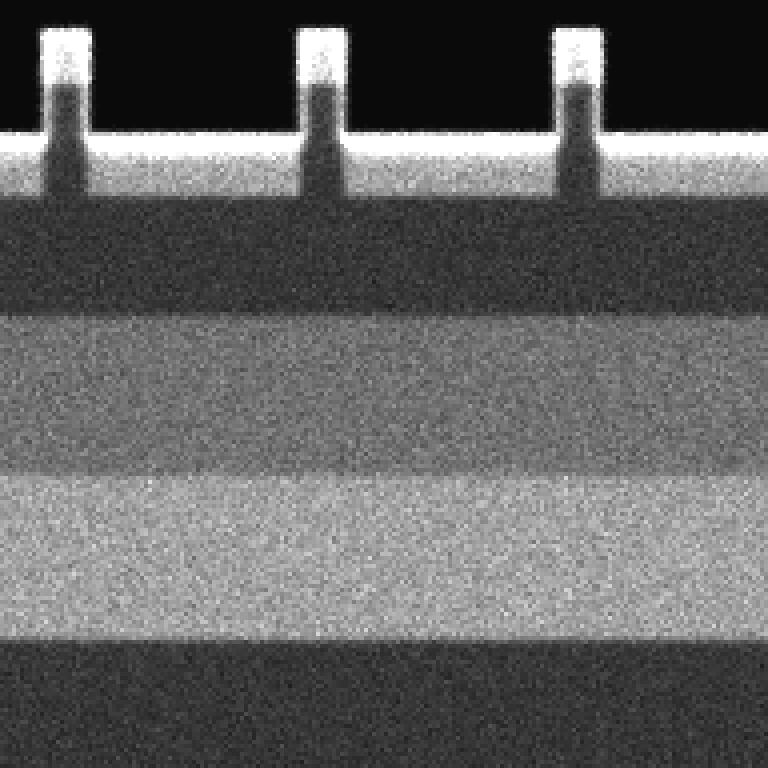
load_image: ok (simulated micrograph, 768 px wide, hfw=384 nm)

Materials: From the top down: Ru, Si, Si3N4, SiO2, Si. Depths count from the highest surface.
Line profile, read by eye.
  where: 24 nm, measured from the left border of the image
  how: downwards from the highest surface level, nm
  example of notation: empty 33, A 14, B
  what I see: Ru 26, Si 116, Si3N4 80, SiO2 82, Si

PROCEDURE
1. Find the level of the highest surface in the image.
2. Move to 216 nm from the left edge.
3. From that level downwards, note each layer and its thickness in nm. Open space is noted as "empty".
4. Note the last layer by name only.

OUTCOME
empty 52, SiO2 30, Si 60, Si3N4 80, SiO2 82, Si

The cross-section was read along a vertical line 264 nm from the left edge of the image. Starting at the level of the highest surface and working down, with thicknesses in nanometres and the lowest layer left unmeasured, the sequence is empty 52, SiO2 30, Si 60, Si3N4 80, SiO2 82, Si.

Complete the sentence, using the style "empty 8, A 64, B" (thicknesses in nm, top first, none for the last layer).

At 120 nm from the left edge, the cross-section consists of empty 52, SiO2 30, Si 60, Si3N4 80, SiO2 82, Si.